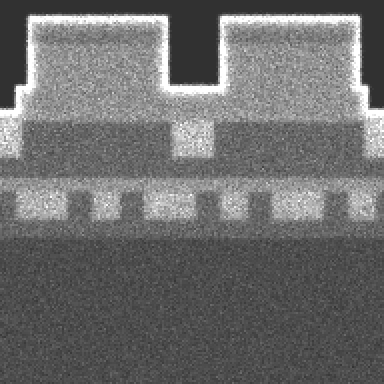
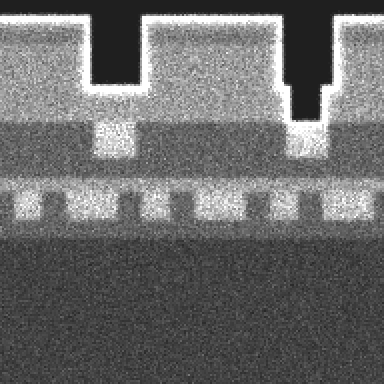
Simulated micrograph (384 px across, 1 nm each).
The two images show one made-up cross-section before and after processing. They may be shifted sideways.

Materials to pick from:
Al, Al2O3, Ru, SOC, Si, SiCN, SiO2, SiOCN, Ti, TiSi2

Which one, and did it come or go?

Al2O3 - removed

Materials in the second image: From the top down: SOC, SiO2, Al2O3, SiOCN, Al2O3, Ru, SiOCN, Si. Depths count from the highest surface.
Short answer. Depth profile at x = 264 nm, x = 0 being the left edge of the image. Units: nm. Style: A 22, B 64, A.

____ SOC 28, SiO2 66, Al2O3 12, SiOCN 56, Al2O3 14, SiOCN 46, Si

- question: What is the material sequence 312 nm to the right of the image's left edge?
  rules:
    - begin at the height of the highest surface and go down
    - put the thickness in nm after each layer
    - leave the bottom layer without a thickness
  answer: empty 106, Ru 36, SiOCN 20, Al2O3 14, SiOCN 46, Si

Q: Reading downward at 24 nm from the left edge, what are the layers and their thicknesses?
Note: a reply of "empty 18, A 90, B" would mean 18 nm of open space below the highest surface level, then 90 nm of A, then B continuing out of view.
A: SOC 28, SiO2 66, Al2O3 12, SiOCN 56, Al2O3 14, Ru 28, SiOCN 18, Si